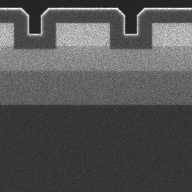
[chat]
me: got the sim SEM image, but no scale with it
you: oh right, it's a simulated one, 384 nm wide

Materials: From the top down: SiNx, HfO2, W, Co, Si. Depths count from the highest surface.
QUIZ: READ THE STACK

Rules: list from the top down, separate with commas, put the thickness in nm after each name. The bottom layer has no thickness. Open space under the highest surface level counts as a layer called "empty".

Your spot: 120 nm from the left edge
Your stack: SiNx 30, HfO2 46, W 50, Co 68, Si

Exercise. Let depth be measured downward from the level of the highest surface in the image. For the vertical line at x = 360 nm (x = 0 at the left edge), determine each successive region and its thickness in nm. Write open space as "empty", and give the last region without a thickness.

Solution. SiNx 30, HfO2 46, W 50, Co 68, Si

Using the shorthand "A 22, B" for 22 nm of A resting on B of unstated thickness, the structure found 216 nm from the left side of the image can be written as SiNx 30, HfO2 46, W 50, Co 68, Si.